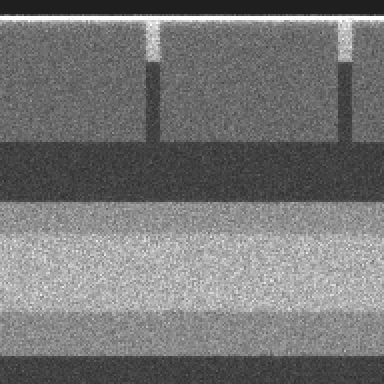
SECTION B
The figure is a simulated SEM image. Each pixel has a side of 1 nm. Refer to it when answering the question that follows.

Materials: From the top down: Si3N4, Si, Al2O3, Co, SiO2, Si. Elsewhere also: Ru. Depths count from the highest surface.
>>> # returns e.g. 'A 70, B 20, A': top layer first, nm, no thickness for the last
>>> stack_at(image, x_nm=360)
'Si3N4 126, Si 60, Al2O3 32, Co 78, SiO2 44, Si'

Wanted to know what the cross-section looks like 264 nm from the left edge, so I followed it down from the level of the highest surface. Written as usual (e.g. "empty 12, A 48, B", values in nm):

Si3N4 126, Si 60, Al2O3 32, Co 78, SiO2 44, Si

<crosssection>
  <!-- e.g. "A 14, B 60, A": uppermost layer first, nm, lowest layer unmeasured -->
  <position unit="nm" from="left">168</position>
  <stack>Si3N4 126, Si 60, Al2O3 32, Co 78, SiO2 44, Si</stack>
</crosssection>